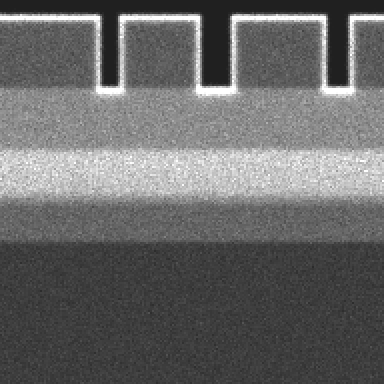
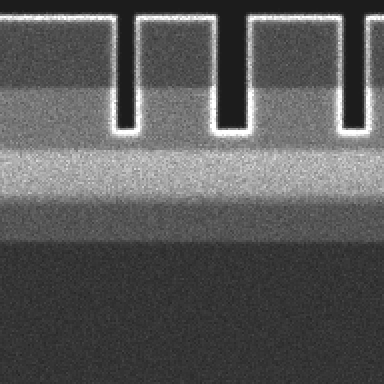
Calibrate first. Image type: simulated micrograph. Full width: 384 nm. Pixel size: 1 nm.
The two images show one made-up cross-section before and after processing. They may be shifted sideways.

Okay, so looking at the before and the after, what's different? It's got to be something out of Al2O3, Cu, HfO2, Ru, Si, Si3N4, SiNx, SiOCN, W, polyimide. Al2O3, removed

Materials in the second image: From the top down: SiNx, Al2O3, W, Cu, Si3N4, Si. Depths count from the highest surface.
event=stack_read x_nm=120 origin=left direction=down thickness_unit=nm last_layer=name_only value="empty 114, Al2O3 20, W 46, Cu 8, Si3N4 38, Si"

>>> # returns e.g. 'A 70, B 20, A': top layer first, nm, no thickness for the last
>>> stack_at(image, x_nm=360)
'empty 114, Al2O3 20, W 46, Cu 8, Si3N4 38, Si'